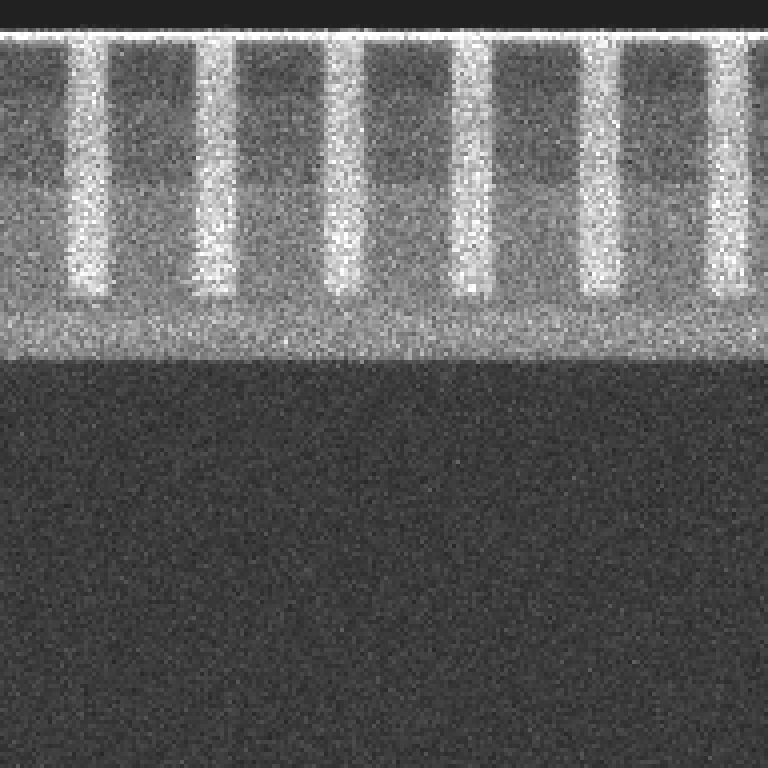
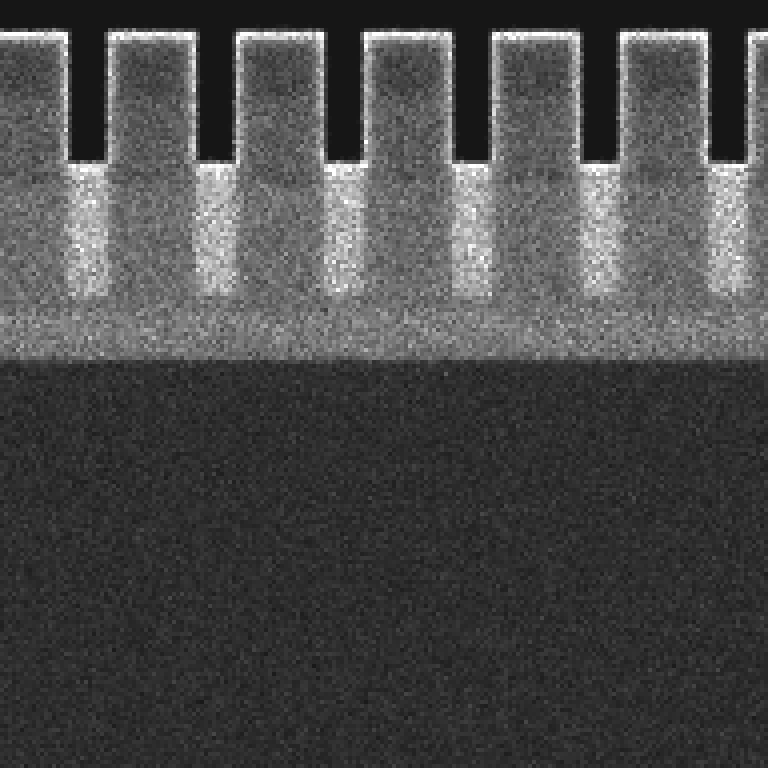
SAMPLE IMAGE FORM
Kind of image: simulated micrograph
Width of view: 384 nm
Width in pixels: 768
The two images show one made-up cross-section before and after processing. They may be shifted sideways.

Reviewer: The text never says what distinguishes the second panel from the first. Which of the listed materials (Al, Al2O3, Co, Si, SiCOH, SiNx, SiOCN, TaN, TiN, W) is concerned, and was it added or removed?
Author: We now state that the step removed W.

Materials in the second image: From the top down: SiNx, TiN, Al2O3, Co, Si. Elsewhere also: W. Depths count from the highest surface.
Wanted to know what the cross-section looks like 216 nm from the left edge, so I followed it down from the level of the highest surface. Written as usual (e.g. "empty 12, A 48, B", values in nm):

SiNx 32, TiN 44, Al2O3 64, Co 24, Si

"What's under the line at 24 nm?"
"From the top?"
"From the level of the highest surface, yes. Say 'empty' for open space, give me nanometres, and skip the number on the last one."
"SiNx 32, TiN 44, Al2O3 64, Co 24, Si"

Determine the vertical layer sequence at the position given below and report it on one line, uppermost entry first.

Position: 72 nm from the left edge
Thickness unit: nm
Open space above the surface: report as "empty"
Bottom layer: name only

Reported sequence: SiNx 32, TiN 44, Al2O3 64, Co 24, Si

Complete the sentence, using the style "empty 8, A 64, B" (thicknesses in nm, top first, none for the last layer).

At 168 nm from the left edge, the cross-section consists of empty 66, W 66, Al2O3 8, Co 24, Si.